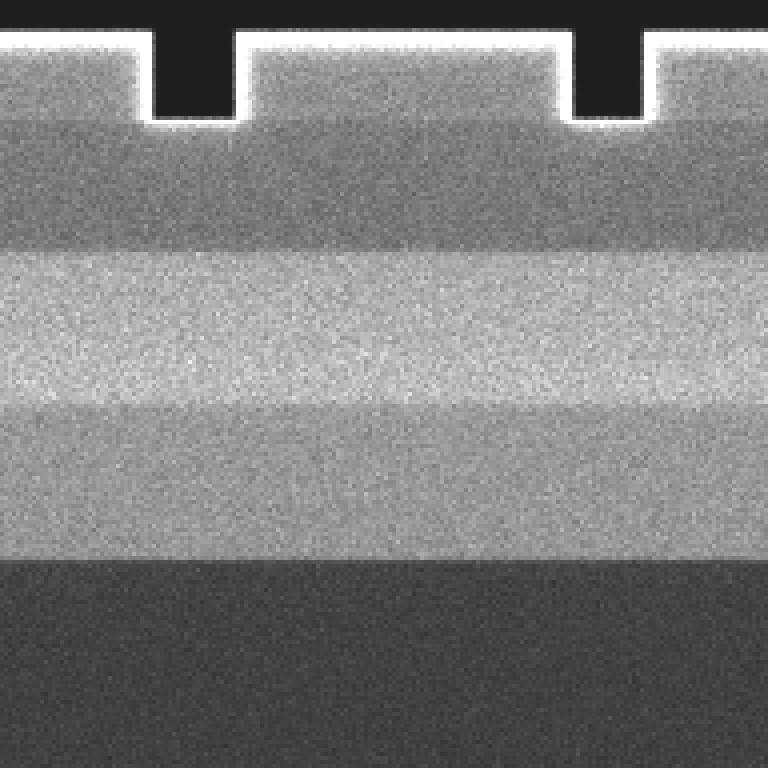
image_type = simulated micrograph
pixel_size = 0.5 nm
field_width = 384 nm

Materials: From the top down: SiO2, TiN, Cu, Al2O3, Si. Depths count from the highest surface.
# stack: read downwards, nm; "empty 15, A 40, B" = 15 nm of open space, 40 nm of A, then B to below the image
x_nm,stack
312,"empty 44, TiN 66, Cu 76, Al2O3 78, Si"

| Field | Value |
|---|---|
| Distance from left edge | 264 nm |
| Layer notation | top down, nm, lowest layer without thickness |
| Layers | SiO2 44, TiN 66, Cu 76, Al2O3 78, Si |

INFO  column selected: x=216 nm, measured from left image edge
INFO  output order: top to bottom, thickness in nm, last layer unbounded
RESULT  SiO2 44, TiN 66, Cu 76, Al2O3 78, Si